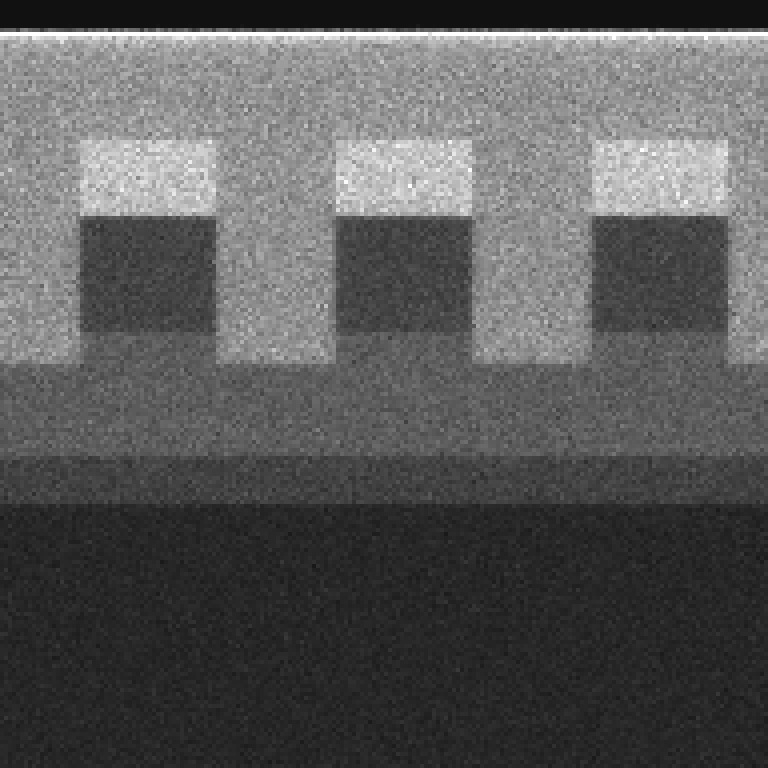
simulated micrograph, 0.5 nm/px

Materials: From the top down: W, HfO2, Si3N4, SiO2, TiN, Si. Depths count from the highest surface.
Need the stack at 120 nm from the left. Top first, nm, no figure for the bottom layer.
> W 166, SiO2 46, TiN 24, Si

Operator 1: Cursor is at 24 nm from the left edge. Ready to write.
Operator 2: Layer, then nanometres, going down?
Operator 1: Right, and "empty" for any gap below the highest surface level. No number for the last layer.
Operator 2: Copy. W 166, SiO2 46, TiN 24, Si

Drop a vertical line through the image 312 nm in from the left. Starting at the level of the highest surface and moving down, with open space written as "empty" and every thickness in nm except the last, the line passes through W 54, HfO2 38, Si3N4 58, SiO2 62, TiN 24, Si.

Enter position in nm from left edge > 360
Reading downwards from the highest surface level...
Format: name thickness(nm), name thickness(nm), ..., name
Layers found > W 54, HfO2 38, Si3N4 58, SiO2 62, TiN 24, Si